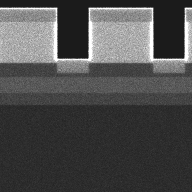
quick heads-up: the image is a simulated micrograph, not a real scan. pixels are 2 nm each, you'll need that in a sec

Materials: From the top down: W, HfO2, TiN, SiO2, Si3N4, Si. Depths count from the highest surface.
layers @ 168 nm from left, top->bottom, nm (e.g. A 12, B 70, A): empty 102, W 28, TiN 8, SiO2 32, Si3N4 24, Si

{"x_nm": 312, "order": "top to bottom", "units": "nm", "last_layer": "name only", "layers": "empty 102, W 28, TiN 8, SiO2 32, Si3N4 24, Si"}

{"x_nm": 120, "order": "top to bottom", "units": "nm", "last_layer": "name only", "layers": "empty 102, W 28, TiN 8, SiO2 32, Si3N4 24, Si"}